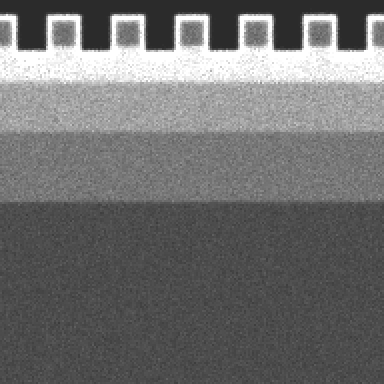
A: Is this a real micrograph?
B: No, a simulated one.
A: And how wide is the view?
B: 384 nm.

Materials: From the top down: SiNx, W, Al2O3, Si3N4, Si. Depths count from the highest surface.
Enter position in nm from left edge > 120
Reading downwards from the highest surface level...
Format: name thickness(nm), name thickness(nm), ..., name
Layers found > SiNx 30, W 36, Al2O3 50, Si3N4 70, Si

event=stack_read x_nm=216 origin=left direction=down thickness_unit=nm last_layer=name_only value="empty 36, W 30, Al2O3 50, Si3N4 70, Si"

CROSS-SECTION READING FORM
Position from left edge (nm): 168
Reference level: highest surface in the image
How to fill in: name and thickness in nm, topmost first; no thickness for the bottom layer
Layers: empty 36, W 30, Al2O3 50, Si3N4 70, Si